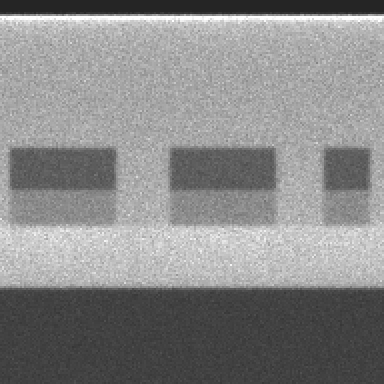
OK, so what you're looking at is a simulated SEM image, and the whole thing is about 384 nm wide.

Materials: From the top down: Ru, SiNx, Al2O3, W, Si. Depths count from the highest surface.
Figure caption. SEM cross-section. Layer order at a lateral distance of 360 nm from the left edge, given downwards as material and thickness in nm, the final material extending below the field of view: Ru 132, SiNx 42, Al2O3 36, W 62, Si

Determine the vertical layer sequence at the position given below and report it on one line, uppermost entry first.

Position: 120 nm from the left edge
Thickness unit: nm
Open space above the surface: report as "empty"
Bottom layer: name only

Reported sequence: Ru 210, W 62, Si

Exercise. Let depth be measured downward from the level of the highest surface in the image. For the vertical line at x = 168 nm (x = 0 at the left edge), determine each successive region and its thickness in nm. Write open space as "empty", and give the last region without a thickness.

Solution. Ru 210, W 62, Si